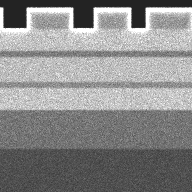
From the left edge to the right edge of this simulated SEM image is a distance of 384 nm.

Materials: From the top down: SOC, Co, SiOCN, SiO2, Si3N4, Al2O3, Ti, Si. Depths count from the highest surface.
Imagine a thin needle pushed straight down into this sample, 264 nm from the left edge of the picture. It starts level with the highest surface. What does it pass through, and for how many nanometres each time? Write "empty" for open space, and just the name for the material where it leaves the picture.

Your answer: empty 42, Co 44, SiOCN 12, SiO2 50, Si3N4 12, Al2O3 44, Ti 78, Si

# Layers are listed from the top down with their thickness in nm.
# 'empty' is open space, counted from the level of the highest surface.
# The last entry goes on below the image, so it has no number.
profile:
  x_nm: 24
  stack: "empty 42, Co 44, SiOCN 12, SiO2 50, Si3N4 12, Al2O3 44, Ti 78, Si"